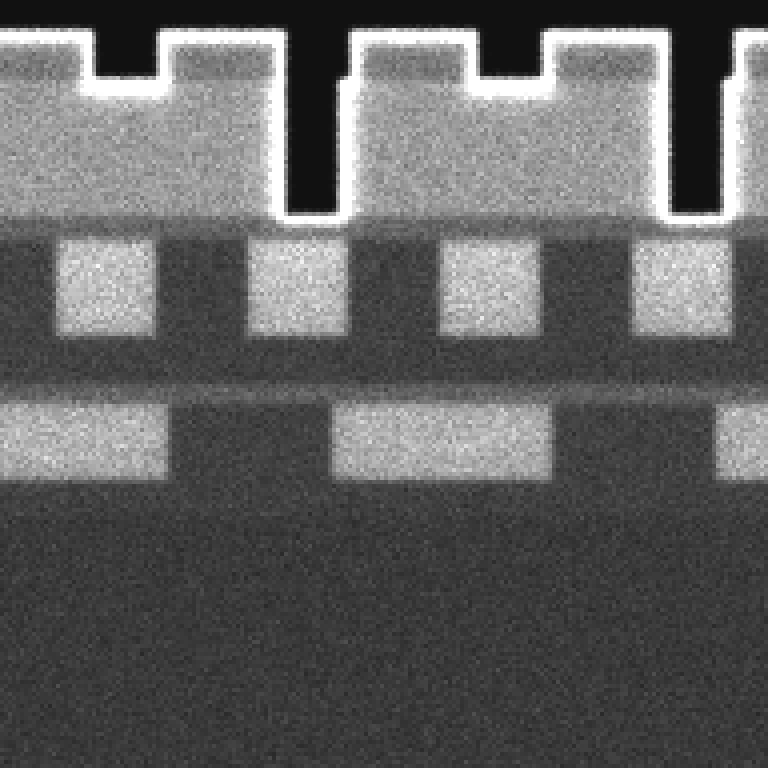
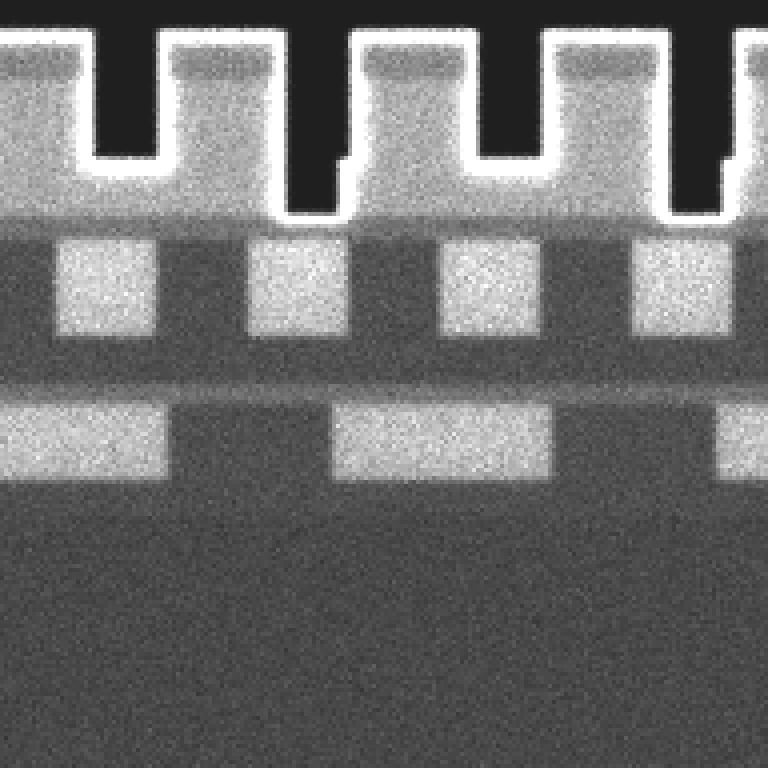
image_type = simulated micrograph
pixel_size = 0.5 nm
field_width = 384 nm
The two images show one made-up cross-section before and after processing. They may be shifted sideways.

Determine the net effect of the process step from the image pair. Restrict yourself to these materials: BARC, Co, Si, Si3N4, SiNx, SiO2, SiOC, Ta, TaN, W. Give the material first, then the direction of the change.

SiO2: removed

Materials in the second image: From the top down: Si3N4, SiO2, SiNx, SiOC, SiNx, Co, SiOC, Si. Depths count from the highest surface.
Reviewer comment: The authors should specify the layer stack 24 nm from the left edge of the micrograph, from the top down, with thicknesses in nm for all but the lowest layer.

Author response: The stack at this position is Si3N4 24, SiO2 68, SiNx 12, SiOC 72, SiNx 10, Co 38, SiOC 18, Si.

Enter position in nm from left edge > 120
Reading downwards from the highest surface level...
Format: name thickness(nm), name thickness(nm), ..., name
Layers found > Si3N4 24, SiO2 68, SiNx 12, SiOC 72, SiNx 10, SiOC 56, Si